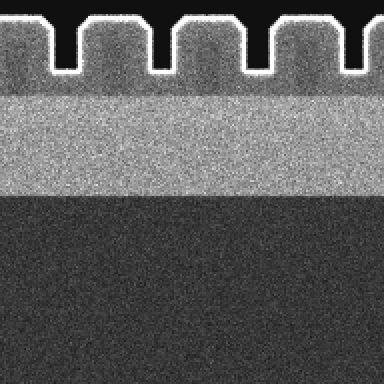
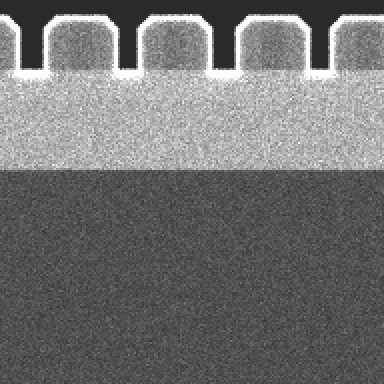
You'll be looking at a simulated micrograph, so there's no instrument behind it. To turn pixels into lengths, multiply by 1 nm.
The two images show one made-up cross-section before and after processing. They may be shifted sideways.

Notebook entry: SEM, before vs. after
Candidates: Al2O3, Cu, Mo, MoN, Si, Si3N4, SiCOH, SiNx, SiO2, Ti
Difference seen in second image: Si3N4 removed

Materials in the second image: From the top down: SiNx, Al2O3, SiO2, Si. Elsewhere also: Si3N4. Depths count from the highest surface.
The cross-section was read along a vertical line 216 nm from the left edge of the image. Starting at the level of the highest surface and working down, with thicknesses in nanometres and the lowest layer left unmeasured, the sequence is empty 54, Al2O3 30, SiO2 70, Si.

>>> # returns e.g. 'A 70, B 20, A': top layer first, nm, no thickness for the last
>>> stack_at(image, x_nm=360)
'SiNx 54, Al2O3 30, SiO2 70, Si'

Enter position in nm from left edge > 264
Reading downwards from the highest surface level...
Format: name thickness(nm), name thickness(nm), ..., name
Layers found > SiNx 54, Al2O3 30, SiO2 70, Si